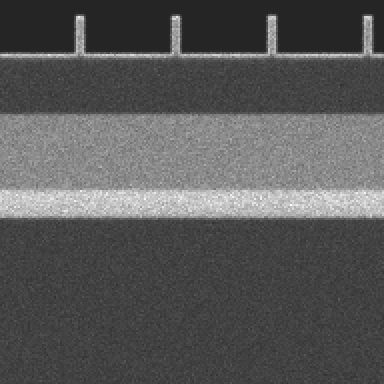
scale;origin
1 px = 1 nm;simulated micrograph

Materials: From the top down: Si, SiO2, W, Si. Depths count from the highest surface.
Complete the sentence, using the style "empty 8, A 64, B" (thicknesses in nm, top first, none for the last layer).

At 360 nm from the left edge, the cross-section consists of empty 38, Si 60, SiO2 76, W 28, Si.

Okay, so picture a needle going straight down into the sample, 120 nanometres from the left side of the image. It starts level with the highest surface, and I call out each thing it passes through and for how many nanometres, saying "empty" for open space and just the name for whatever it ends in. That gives empty 38, Si 60, SiO2 76, W 28, Si